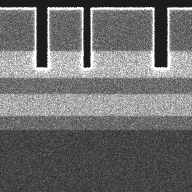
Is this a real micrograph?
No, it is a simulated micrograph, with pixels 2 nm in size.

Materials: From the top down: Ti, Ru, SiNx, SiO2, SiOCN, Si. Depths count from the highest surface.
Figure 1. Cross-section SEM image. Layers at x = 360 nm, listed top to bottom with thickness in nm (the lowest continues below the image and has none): Ti 86, Ru 54, SiNx 32, SiO2 44, SiOCN 28, Si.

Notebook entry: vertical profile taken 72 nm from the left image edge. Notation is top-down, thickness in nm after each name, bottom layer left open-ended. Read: empty 120, Ru 20, SiNx 32, SiO2 44, SiOCN 28, Si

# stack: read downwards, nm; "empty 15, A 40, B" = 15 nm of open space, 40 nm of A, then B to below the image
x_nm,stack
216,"Ti 86, Ru 54, SiNx 32, SiO2 44, SiOCN 28, Si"